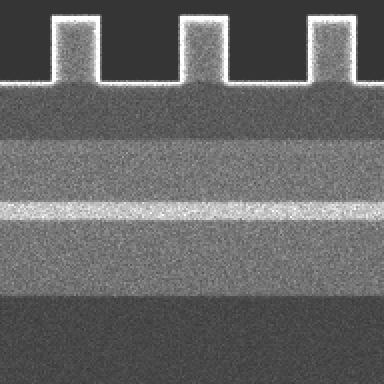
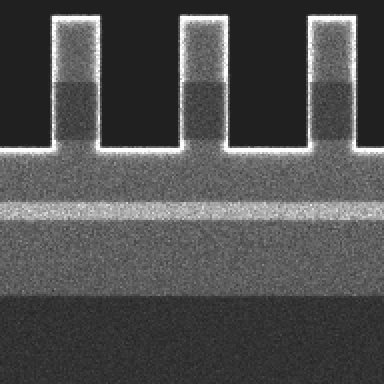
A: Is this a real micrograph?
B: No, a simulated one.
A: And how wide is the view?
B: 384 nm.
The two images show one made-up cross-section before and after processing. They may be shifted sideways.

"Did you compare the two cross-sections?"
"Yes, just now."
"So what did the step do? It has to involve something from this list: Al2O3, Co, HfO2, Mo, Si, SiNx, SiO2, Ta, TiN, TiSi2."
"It removed Al2O3 and SiNx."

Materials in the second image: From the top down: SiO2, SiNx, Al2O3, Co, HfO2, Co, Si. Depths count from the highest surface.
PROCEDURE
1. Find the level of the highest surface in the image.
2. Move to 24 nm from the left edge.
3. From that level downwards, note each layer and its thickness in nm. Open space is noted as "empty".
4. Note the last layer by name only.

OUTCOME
empty 132, Al2O3 6, Co 48, HfO2 18, Co 76, Si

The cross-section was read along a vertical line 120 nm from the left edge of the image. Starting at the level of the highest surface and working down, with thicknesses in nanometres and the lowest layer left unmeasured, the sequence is empty 132, Al2O3 6, Co 48, HfO2 18, Co 76, Si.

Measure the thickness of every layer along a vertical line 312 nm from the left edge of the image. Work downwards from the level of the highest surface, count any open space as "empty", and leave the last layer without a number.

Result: SiO2 66, SiNx 58, Al2O3 14, Co 48, HfO2 18, Co 76, Si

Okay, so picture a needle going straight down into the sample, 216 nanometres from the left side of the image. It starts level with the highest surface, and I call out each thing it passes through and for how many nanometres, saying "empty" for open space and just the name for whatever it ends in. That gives SiO2 66, SiNx 58, Al2O3 14, Co 48, HfO2 18, Co 76, Si